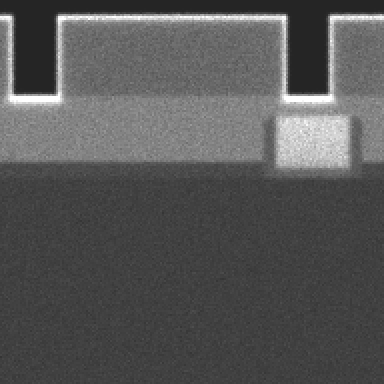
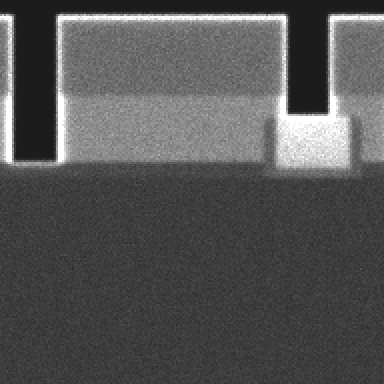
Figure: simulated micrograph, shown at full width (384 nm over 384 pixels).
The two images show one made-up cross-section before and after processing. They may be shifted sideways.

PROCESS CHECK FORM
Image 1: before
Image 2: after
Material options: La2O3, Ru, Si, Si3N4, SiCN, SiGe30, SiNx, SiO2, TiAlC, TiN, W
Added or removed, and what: removed, SiO2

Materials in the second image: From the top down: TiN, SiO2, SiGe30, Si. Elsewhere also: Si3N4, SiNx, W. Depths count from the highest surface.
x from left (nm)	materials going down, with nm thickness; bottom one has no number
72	TiN 80, SiO2 66, SiGe30 16, Si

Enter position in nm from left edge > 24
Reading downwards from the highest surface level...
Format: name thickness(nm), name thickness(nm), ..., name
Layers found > empty 146, SiGe30 16, Si